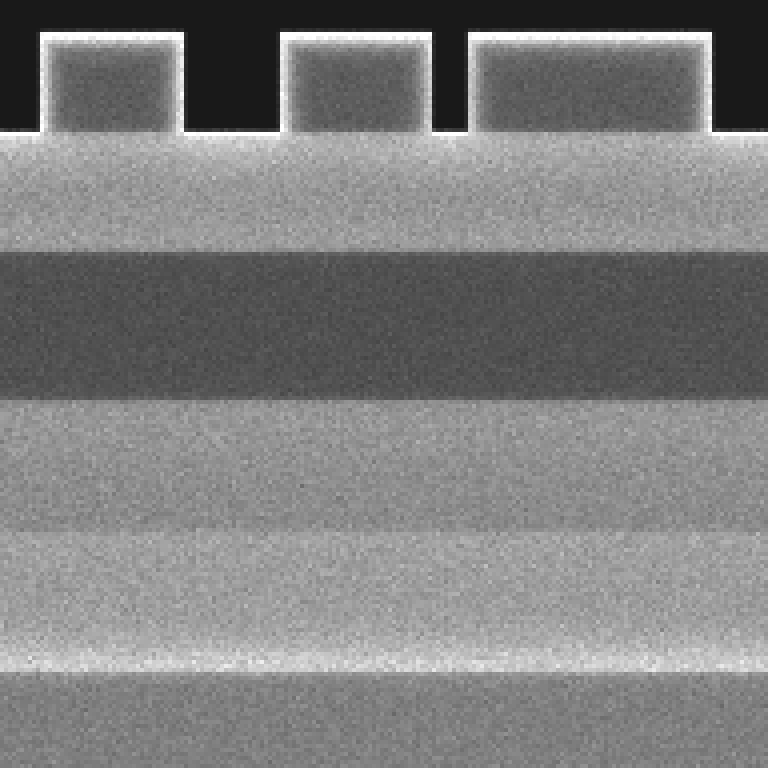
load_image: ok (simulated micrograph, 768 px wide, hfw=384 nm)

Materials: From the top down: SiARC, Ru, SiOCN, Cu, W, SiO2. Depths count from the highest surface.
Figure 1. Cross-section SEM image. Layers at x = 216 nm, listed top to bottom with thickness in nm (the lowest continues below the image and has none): empty 50, Ru 60, SiOCN 74, Cu 66, W 70, SiO2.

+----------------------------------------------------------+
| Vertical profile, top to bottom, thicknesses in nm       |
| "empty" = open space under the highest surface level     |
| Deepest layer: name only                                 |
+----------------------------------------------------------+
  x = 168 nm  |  SiARC 50, Ru 60, SiOCN 74, Cu 66, W 70, SiO2